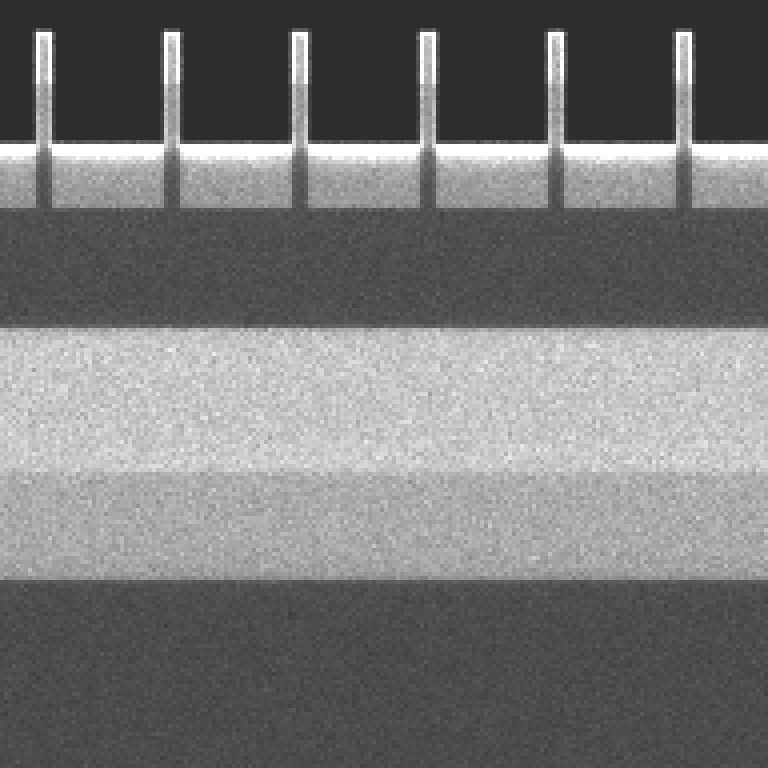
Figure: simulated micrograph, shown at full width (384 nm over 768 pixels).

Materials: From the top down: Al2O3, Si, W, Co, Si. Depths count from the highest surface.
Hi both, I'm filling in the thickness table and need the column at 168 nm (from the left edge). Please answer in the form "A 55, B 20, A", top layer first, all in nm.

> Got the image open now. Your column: empty 56, Al2O3 32, Si 60, W 72, Co 54, Si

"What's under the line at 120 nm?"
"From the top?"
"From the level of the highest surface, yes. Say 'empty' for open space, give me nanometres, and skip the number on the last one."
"empty 56, Al2O3 32, Si 60, W 72, Co 54, Si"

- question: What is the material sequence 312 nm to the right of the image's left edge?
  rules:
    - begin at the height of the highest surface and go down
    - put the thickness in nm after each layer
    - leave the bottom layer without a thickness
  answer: empty 56, Al2O3 32, Si 60, W 72, Co 54, Si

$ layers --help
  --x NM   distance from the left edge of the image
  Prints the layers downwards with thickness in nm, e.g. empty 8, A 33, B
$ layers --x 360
empty 56, Al2O3 32, Si 60, W 72, Co 54, Si